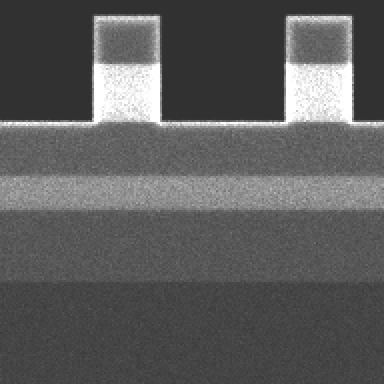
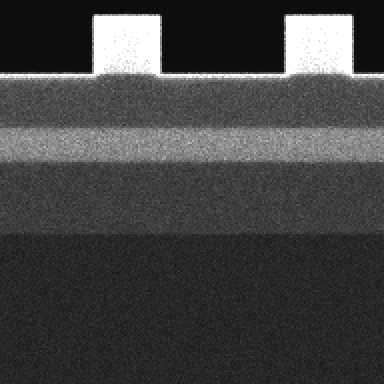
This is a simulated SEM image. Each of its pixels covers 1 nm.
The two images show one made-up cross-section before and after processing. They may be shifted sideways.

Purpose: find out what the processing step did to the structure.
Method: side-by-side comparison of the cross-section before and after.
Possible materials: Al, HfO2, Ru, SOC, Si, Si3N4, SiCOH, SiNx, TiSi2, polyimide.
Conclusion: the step removed SOC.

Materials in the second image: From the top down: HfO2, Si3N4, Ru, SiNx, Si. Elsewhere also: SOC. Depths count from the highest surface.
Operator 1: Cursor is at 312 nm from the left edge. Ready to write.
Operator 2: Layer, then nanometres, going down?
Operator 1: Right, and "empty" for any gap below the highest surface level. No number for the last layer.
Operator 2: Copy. HfO2 58, Si3N4 54, Ru 34, SiNx 72, Si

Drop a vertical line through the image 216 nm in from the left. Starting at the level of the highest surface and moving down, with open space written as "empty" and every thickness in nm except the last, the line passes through empty 58, Si3N4 54, Ru 34, SiNx 72, Si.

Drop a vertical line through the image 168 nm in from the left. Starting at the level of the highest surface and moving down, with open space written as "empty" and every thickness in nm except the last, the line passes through empty 58, Si3N4 54, Ru 34, SiNx 72, Si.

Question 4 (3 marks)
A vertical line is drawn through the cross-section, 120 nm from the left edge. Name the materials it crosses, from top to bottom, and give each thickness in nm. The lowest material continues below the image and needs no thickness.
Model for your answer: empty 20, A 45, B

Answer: HfO2 58, Si3N4 54, Ru 34, SiNx 72, Si